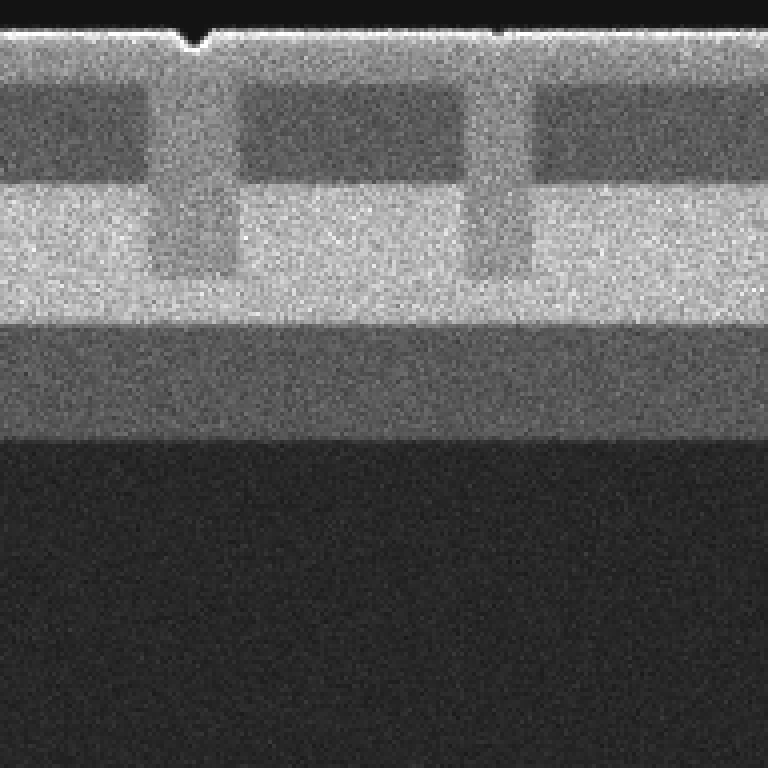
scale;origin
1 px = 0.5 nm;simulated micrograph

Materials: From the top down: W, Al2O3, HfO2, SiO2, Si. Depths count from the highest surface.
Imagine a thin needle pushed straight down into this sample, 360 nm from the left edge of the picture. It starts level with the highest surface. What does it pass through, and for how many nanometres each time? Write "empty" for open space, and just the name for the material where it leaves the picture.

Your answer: W 26, Al2O3 50, HfO2 70, SiO2 58, Si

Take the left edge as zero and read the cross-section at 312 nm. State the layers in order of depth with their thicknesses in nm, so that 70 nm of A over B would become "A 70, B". W 26, Al2O3 50, HfO2 70, SiO2 58, Si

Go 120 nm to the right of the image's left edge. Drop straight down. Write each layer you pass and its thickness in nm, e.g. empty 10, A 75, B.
W 26, Al2O3 50, HfO2 70, SiO2 58, Si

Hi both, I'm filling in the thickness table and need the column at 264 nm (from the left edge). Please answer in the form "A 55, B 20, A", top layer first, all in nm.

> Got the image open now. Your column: W 124, HfO2 22, SiO2 58, Si